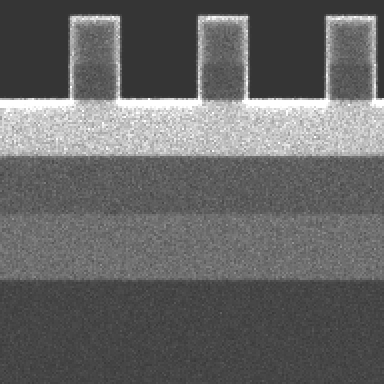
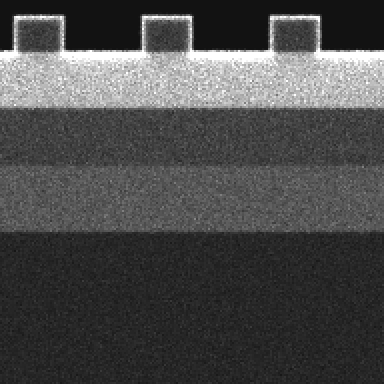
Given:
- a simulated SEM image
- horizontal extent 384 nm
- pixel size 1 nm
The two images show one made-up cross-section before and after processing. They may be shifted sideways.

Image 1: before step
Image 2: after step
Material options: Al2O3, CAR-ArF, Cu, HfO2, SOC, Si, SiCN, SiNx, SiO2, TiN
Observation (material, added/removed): SOC, removed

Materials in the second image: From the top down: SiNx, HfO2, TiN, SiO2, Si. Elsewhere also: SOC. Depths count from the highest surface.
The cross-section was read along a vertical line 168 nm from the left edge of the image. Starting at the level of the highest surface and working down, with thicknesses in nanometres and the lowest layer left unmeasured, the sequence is SiNx 36, HfO2 56, TiN 58, SiO2 66, Si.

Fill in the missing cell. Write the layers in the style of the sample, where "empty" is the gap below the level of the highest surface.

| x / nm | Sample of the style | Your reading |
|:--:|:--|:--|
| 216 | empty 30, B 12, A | empty 36, HfO2 56, TiN 58, SiO2 66, Si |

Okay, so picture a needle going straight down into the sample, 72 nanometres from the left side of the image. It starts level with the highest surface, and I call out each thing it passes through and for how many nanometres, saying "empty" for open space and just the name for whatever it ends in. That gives empty 36, HfO2 56, TiN 58, SiO2 66, Si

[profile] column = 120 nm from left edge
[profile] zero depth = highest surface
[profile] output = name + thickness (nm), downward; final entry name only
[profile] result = empty 36, HfO2 56, TiN 58, SiO2 66, Si